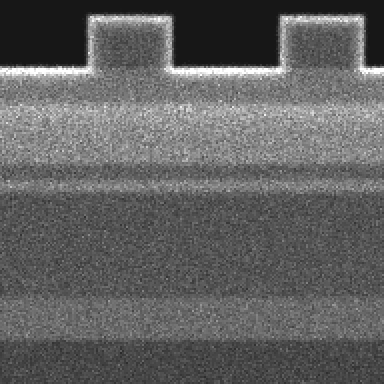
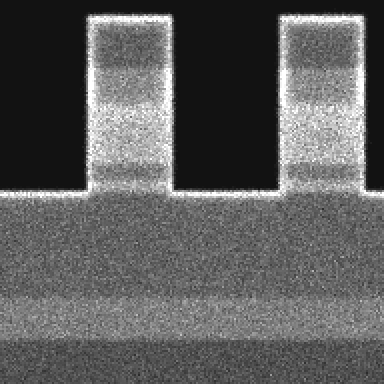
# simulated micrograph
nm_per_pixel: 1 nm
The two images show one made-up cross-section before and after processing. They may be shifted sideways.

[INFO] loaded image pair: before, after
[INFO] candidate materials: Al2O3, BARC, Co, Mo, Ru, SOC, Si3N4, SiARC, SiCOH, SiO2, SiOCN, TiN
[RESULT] removed Al2O3 and Co and Ru and TiN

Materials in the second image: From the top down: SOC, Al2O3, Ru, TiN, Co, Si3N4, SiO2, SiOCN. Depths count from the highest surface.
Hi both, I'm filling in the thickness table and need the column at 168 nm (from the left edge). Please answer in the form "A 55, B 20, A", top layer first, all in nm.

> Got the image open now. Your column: SOC 52, Al2O3 36, Ru 60, TiN 16, Co 12, Si3N4 106, SiO2 42, SiOCN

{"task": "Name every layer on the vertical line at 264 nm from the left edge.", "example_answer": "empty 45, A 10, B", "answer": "empty 176, Si3N4 106, SiO2 42, SiOCN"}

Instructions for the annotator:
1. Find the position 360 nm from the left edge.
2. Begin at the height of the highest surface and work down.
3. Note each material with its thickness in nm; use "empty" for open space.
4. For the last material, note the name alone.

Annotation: SOC 52, Al2O3 36, Ru 60, TiN 16, Co 12, Si3N4 106, SiO2 42, SiOCN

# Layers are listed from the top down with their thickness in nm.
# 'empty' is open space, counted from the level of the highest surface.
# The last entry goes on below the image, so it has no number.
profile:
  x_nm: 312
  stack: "SOC 52, Al2O3 36, Ru 60, TiN 16, Co 12, Si3N4 106, SiO2 42, SiOCN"